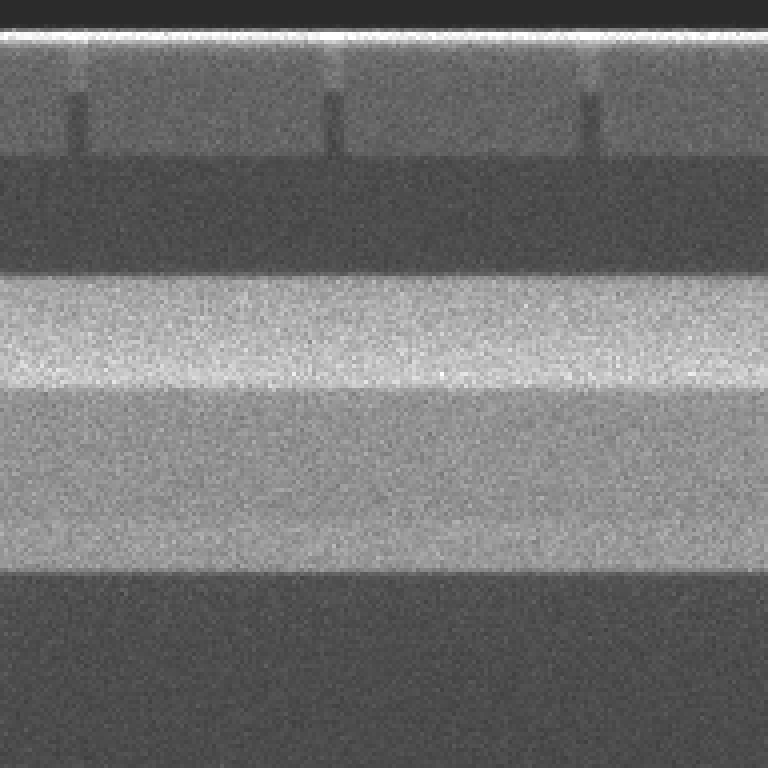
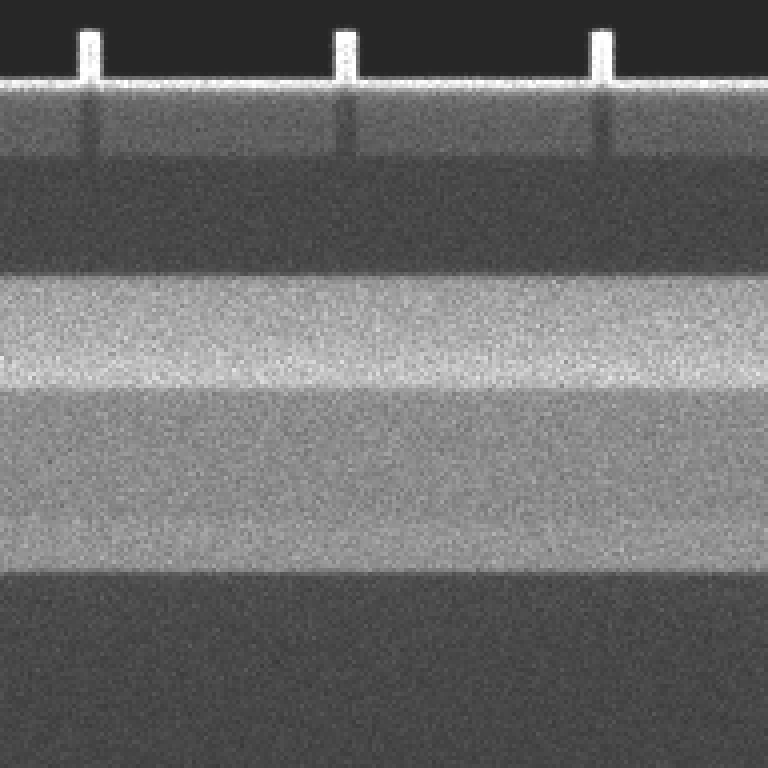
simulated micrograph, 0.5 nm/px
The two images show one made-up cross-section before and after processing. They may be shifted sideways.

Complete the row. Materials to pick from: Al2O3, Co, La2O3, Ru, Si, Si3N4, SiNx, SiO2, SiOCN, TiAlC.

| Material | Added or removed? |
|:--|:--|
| SiOCN | removed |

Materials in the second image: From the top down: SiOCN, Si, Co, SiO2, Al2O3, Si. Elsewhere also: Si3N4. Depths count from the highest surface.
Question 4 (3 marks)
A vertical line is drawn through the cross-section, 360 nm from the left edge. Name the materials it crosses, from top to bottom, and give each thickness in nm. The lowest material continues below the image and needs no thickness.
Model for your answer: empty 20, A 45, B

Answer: empty 24, SiOCN 38, Si 60, Co 56, SiO2 66, Al2O3 26, Si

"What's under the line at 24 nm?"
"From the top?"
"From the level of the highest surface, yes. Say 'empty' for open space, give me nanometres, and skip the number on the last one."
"empty 24, SiOCN 38, Si 60, Co 56, SiO2 66, Al2O3 26, Si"